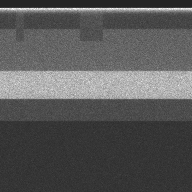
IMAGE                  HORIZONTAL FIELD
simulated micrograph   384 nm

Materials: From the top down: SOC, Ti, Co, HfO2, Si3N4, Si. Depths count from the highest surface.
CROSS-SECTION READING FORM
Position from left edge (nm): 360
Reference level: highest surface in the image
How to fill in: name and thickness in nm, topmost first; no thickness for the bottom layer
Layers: SOC 8, Ti 34, Co 84, HfO2 56, Si3N4 44, Si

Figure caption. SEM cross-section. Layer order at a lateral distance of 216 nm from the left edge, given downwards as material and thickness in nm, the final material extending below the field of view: SOC 8, Ti 34, Co 84, HfO2 56, Si3N4 44, Si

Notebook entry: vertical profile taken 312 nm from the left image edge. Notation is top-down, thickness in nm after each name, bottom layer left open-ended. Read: SOC 8, Ti 34, Co 84, HfO2 56, Si3N4 44, Si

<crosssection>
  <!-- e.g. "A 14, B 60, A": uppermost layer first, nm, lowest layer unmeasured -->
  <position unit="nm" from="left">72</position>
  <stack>SOC 8, Ti 34, Co 84, HfO2 56, Si3N4 44, Si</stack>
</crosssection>